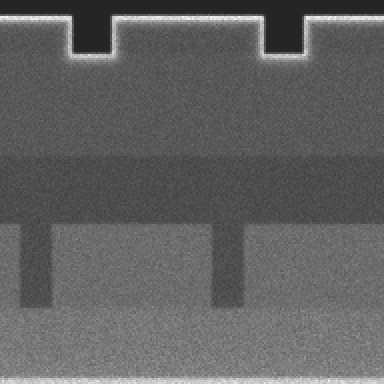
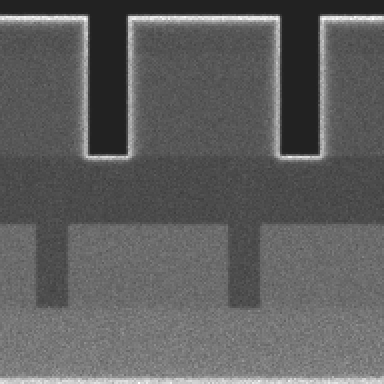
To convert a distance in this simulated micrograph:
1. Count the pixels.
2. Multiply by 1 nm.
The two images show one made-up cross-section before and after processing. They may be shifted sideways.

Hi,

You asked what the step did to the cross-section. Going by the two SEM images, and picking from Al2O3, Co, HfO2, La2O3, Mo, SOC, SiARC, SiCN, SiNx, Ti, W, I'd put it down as SOC, removed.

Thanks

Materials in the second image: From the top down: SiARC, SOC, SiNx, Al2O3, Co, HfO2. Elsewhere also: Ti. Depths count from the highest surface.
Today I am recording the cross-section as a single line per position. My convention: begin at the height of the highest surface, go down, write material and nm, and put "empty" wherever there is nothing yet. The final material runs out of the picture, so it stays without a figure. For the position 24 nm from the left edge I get SiARC 38, SOC 102, SiNx 68, Al2O3 84, Co 70, HfO2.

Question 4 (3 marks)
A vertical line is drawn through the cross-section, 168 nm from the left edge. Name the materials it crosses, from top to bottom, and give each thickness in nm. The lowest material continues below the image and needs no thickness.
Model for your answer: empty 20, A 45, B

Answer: SiARC 38, SOC 102, SiNx 68, Al2O3 84, Co 70, HfO2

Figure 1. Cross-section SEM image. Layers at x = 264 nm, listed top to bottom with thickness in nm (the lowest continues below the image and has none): SiARC 38, SOC 102, SiNx 68, Al2O3 84, Co 70, HfO2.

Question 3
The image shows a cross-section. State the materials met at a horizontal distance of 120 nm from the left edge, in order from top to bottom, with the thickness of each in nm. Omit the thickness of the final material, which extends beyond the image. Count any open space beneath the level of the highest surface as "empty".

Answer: empty 140, SiNx 68, Al2O3 84, Co 70, HfO2